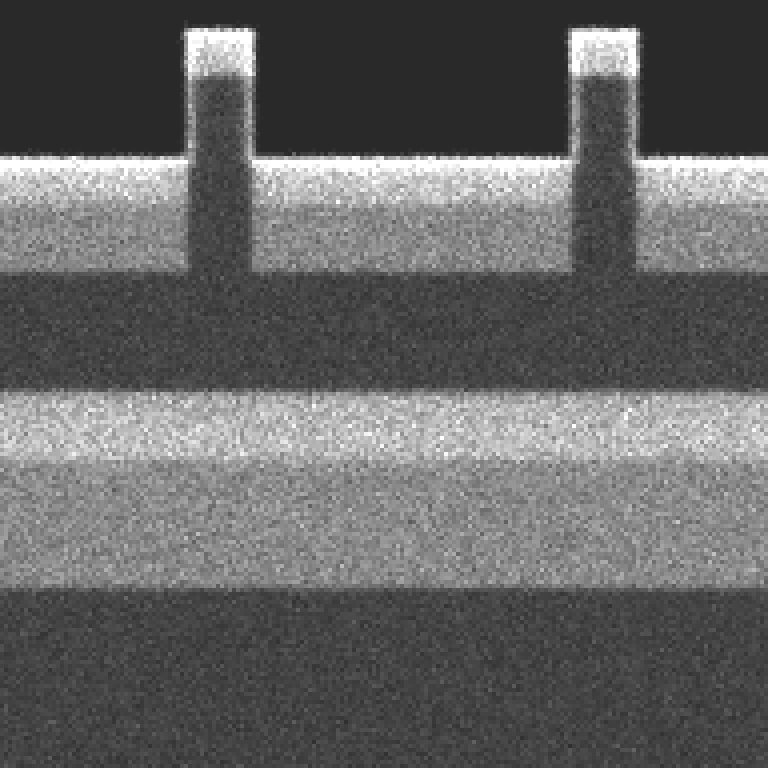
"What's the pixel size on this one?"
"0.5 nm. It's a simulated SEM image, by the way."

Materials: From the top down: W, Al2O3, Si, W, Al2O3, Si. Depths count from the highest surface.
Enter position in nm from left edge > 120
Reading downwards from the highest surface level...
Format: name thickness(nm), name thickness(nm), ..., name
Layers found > W 22, Si 158, W 34, Al2O3 64, Si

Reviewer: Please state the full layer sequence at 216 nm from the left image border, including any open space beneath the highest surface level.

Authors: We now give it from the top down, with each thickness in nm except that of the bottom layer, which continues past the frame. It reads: empty 64, W 22, Al2O3 34, Si 60, W 34, Al2O3 64, Si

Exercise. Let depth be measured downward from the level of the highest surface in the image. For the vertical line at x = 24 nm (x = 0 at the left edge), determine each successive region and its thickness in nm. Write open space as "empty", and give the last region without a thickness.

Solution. empty 64, W 22, Al2O3 34, Si 60, W 34, Al2O3 64, Si